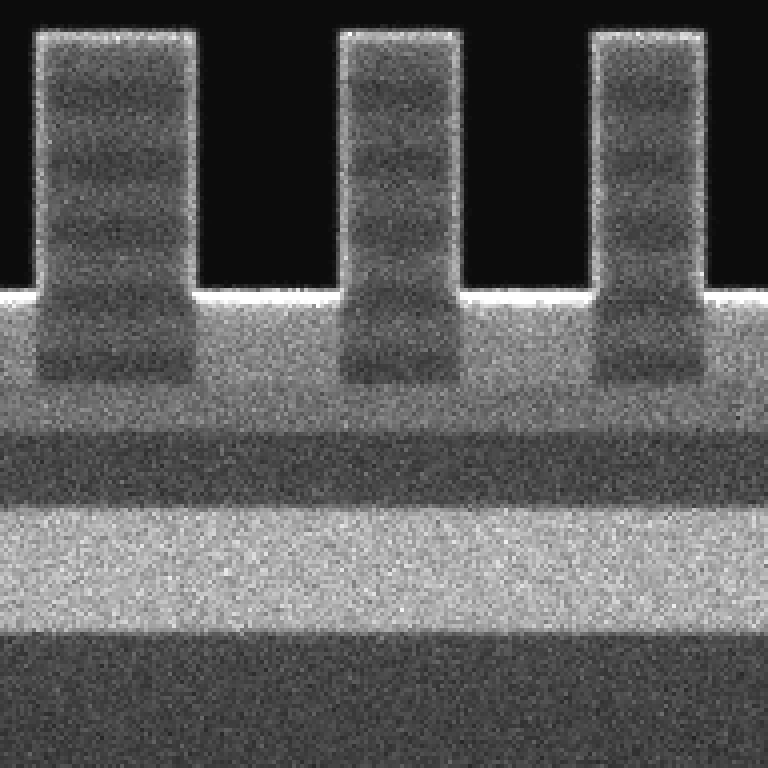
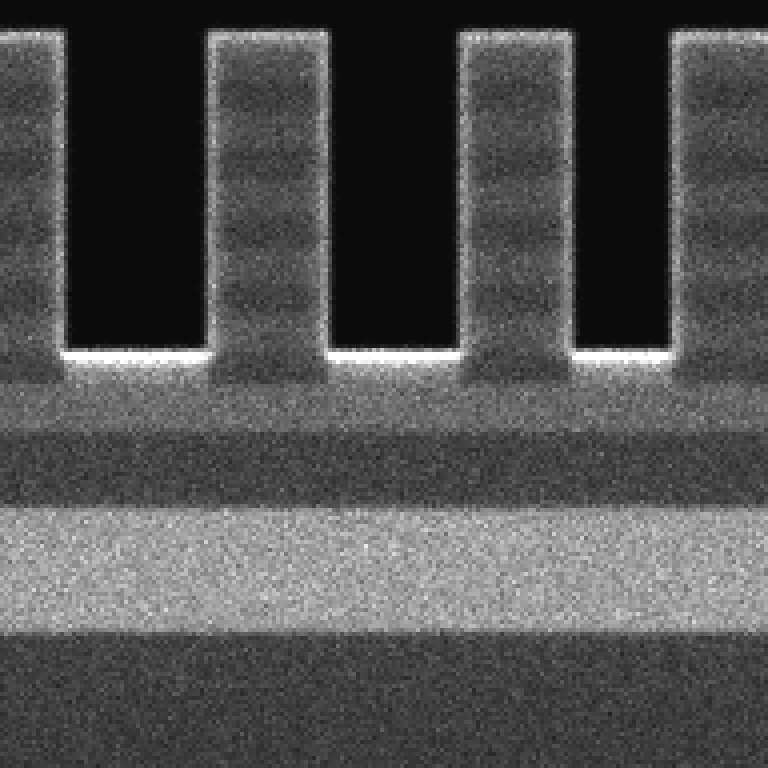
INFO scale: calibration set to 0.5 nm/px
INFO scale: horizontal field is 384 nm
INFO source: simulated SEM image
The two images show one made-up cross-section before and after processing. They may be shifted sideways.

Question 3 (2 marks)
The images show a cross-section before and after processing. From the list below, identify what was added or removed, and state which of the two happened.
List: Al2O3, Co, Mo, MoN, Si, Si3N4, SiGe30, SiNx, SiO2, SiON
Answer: Si3N4 was removed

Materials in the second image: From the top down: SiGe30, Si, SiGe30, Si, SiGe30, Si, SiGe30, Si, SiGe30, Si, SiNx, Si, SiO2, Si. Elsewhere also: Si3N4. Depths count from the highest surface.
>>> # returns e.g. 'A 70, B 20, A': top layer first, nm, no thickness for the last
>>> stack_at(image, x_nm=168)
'empty 160, Si3N4 16, SiNx 24, Si 38, SiO2 62, Si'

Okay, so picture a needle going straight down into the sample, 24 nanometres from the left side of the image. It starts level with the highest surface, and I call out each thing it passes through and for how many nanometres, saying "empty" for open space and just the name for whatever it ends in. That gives SiGe30 24, Si 16, SiGe30 18, Si 16, SiGe30 18, Si 16, SiGe30 18, Si 16, SiGe30 18, Si 16, SiNx 24, Si 38, SiO2 62, Si